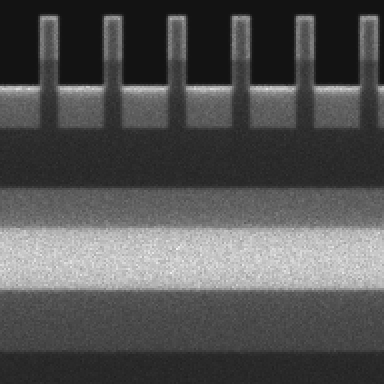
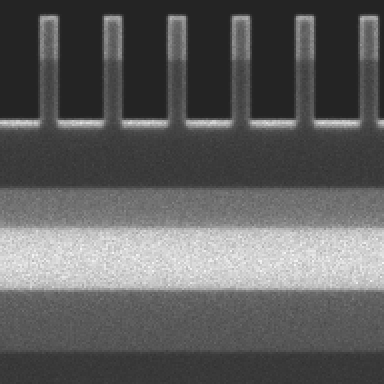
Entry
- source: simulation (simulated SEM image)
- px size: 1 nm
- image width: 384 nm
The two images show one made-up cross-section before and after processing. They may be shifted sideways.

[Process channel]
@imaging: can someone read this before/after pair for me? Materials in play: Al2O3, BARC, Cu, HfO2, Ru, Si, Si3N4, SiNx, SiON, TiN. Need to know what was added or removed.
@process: Al2O3 removed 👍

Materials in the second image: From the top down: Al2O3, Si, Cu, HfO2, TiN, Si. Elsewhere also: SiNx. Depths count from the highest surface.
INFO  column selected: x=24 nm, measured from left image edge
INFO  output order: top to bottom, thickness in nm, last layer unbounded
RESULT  empty 104, Al2O3 8, Si 60, Cu 40, HfO2 62, TiN 62, Si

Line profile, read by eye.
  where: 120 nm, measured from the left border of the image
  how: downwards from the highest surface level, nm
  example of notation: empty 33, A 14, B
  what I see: SiNx 44, Si 128, Cu 40, HfO2 62, TiN 62, Si